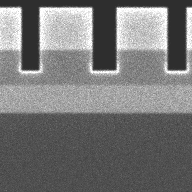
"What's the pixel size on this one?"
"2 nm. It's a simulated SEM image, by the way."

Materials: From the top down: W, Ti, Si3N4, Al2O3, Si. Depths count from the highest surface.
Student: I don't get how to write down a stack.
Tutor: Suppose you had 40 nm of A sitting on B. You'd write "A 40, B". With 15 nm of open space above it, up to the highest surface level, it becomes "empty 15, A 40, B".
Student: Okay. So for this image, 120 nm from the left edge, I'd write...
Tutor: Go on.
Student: W 84, Ti 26, Si3N4 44, Al2O3 56, Si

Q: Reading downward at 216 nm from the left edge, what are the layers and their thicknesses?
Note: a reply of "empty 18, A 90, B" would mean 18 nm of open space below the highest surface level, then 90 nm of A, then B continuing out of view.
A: empty 126, Si3N4 28, Al2O3 56, Si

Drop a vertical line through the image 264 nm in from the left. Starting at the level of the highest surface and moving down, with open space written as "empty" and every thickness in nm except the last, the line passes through W 84, Ti 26, Si3N4 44, Al2O3 56, Si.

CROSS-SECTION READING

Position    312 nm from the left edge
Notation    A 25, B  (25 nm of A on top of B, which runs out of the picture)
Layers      W 84, Ti 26, Si3N4 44, Al2O3 56, Si